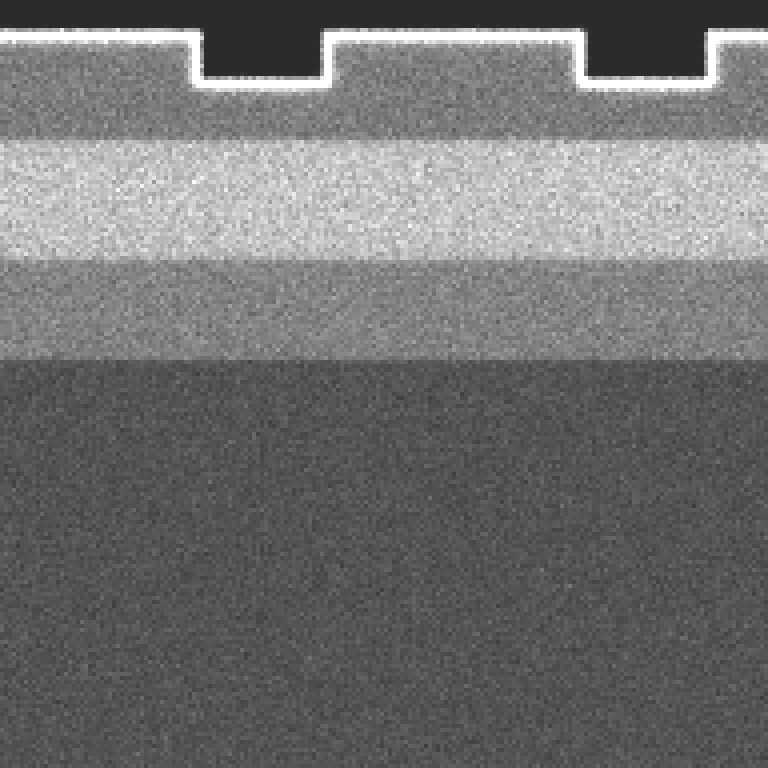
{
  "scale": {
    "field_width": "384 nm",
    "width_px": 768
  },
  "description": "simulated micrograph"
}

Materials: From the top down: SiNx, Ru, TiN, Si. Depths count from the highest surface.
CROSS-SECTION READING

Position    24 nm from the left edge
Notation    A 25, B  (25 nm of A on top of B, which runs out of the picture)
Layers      SiNx 54, Ru 60, TiN 50, Si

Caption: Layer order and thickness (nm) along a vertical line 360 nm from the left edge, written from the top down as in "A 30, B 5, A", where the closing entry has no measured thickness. SiNx 54, Ru 60, TiN 50, Si